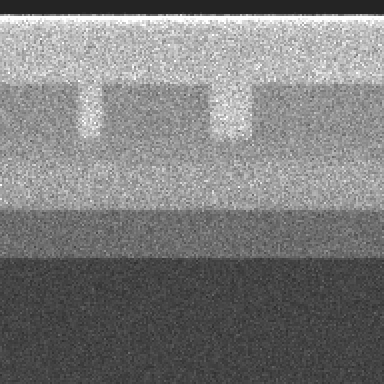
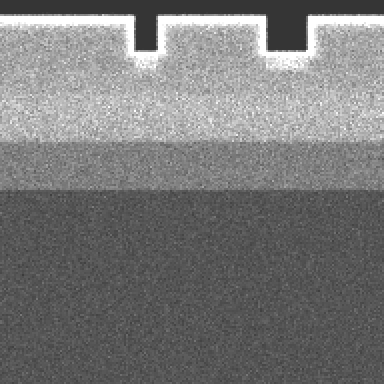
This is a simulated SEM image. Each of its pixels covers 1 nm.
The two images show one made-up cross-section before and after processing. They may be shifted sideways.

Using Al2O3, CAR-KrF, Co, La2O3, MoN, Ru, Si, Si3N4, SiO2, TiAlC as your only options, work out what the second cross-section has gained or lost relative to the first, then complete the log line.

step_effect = removed Ru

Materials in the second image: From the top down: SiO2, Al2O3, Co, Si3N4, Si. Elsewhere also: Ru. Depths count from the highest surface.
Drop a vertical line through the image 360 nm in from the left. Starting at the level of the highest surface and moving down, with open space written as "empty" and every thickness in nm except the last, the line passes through SiO2 54, Al2O3 24, Co 48, Si3N4 48, Si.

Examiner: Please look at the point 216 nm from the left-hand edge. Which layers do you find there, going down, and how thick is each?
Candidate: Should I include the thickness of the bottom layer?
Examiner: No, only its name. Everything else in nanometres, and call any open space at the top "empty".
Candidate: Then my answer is SiO2 54, Al2O3 24, Co 48, Si3N4 48, Si